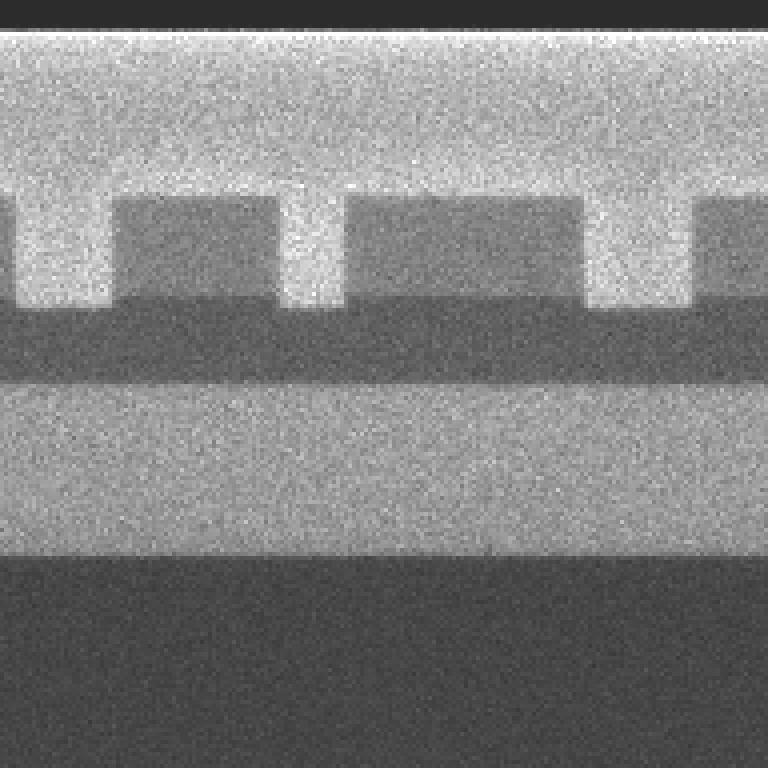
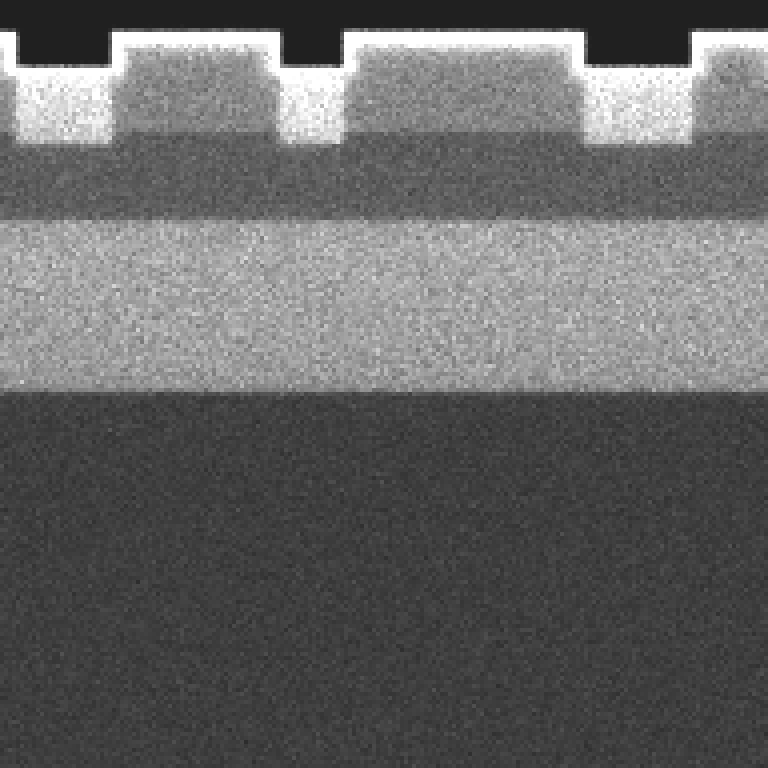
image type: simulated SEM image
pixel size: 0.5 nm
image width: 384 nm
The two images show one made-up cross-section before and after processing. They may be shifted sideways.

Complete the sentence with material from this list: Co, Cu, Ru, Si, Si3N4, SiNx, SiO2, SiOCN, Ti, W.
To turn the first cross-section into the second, W must be removed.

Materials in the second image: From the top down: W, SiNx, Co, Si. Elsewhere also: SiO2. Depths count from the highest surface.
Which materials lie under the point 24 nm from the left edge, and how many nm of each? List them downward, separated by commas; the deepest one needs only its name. empty 18, W 38, SiNx 38, Co 86, Si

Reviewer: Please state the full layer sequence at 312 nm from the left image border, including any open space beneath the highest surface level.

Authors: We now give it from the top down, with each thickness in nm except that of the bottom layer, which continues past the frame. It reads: empty 18, W 38, SiNx 38, Co 86, Si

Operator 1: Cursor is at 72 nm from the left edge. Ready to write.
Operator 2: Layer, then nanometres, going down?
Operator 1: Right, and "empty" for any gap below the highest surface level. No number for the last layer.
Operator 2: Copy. SiO2 50, SiNx 44, Co 86, Si